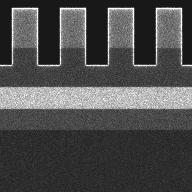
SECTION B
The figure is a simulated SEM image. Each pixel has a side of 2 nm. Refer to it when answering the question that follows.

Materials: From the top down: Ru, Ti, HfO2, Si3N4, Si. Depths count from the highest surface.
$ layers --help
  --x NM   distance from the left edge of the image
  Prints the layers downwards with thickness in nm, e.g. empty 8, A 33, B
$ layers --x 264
Ru 80, Ti 78, HfO2 44, Si3N4 42, Si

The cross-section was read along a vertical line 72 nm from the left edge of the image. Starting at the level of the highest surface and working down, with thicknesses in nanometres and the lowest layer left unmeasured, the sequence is Ru 80, Ti 78, HfO2 44, Si3N4 42, Si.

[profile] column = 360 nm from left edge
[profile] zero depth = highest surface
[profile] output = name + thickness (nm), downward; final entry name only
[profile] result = Ru 80, Ti 78, HfO2 44, Si3N4 42, Si